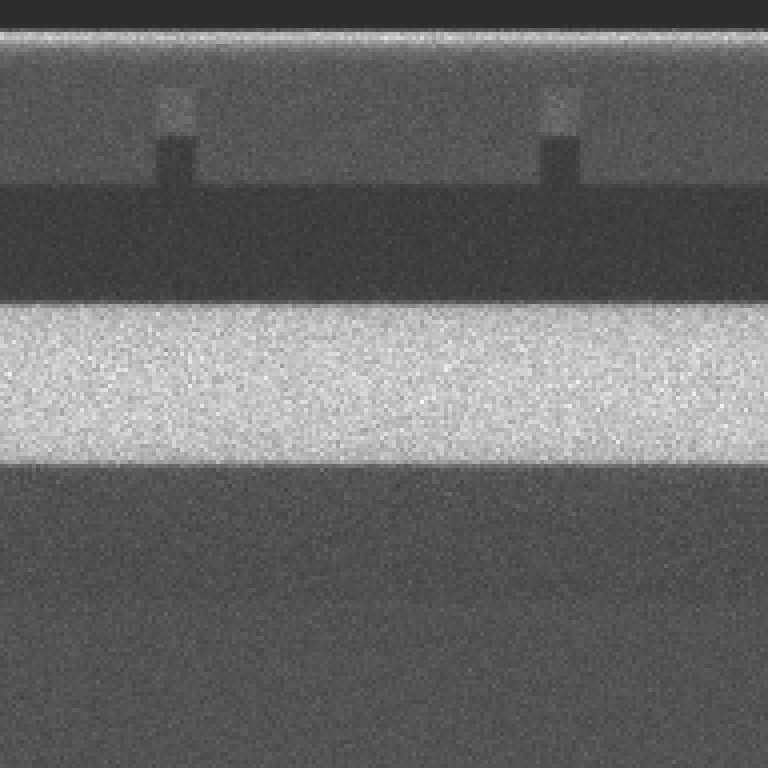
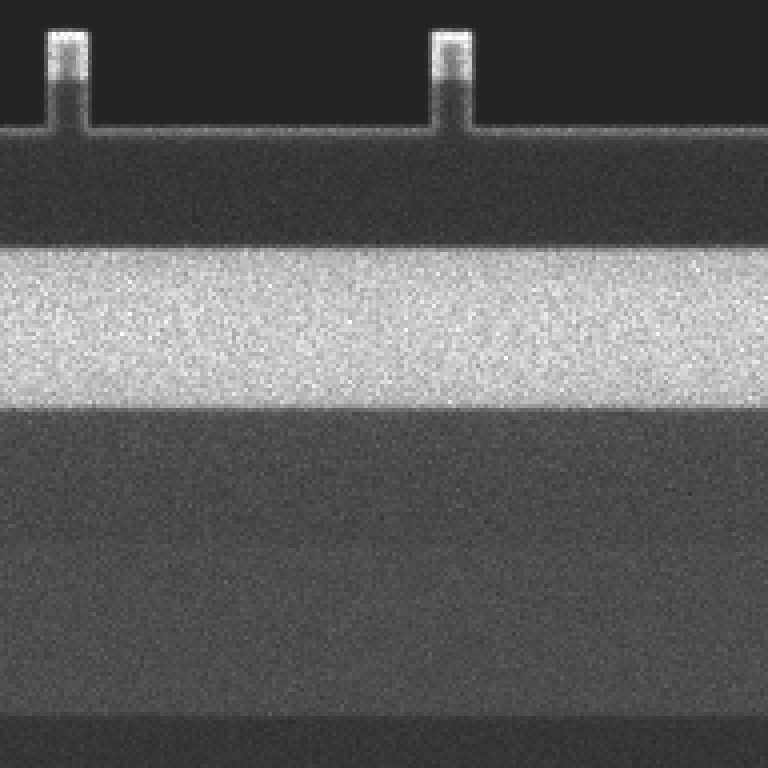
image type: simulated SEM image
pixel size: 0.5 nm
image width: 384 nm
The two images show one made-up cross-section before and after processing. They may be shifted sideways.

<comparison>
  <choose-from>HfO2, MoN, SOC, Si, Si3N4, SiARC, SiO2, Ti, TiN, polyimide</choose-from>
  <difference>SOC removed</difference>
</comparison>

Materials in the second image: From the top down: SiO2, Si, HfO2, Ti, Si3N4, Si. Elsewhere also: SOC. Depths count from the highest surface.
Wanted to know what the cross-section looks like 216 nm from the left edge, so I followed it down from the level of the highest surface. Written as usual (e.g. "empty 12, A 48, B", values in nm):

SiO2 24, Si 84, HfO2 80, Ti 68, Si3N4 86, Si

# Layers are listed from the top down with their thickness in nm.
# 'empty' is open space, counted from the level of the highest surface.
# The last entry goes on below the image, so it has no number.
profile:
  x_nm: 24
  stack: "SiO2 24, Si 84, HfO2 80, Ti 68, Si3N4 86, Si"